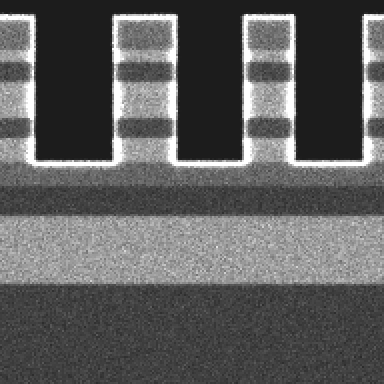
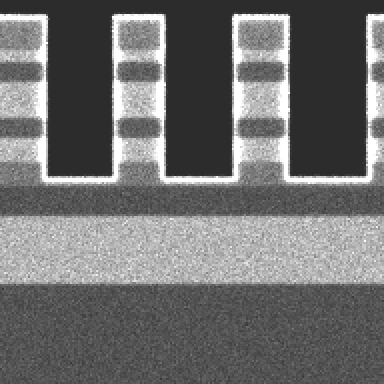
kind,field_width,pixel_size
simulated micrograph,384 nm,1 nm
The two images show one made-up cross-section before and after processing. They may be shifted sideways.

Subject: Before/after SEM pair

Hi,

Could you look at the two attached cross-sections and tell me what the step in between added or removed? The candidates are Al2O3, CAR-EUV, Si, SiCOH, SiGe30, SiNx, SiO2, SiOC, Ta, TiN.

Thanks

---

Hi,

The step removed SiNx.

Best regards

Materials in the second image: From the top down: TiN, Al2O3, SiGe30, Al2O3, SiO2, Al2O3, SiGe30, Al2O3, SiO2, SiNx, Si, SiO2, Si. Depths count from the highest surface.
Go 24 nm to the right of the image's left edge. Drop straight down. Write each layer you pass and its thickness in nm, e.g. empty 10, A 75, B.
TiN 34, Al2O3 12, SiGe30 20, Al2O3 12, SiO2 12, Al2O3 12, SiGe30 20, Al2O3 12, SiO2 12, SiNx 24, Si 30, SiO2 68, Si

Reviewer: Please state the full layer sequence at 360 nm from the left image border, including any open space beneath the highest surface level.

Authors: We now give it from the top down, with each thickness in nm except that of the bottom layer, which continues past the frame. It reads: empty 162, SiNx 8, Si 30, SiO2 68, Si